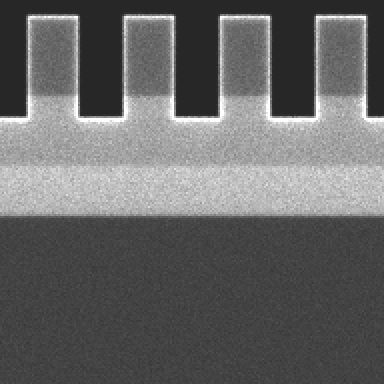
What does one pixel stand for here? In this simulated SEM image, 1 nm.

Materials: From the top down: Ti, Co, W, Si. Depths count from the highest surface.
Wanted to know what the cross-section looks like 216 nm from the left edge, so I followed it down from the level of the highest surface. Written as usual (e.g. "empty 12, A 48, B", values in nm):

empty 102, Co 48, W 50, Si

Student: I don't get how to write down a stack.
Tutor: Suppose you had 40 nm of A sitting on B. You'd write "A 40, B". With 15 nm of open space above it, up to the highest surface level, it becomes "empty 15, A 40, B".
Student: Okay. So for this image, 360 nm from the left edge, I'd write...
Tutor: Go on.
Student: Ti 80, Co 70, W 50, Si